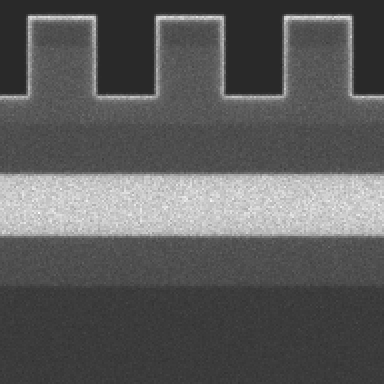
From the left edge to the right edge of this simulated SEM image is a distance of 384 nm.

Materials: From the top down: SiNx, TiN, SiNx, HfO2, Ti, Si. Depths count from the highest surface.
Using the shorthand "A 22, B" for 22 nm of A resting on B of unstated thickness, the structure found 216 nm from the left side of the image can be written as SiNx 30, TiN 78, SiNx 50, HfO2 62, Ti 50, Si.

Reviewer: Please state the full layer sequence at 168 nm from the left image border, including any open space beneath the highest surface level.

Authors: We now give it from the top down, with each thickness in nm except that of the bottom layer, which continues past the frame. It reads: SiNx 30, TiN 78, SiNx 50, HfO2 62, Ti 50, Si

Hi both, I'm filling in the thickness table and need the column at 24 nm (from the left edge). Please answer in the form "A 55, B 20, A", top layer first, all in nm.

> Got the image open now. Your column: empty 80, TiN 28, SiNx 50, HfO2 62, Ti 50, Si